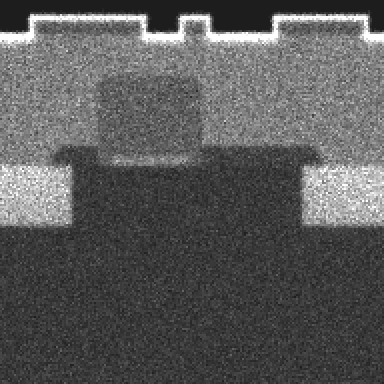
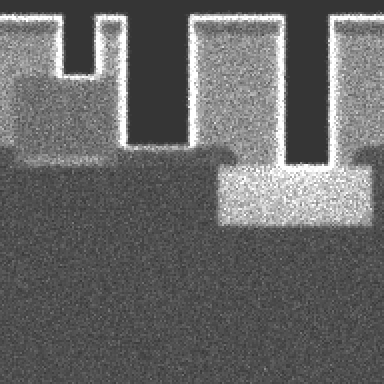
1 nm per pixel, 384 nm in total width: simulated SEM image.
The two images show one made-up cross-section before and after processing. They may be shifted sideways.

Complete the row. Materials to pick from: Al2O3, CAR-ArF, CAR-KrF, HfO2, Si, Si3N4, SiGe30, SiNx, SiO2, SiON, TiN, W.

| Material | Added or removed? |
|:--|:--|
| SiO2 | removed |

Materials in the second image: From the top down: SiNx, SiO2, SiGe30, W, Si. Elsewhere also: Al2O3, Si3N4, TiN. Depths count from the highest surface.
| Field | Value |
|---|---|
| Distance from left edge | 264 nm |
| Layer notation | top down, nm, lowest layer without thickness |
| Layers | SiNx 18, SiO2 132, W 60, Si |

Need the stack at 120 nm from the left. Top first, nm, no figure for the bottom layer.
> SiNx 18, SiO2 112, SiGe30 20, Si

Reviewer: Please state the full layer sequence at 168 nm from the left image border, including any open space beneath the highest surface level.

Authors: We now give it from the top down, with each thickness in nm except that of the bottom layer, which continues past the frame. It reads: empty 130, SiGe30 20, Si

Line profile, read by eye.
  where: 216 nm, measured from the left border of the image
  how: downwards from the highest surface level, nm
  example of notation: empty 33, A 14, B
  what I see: SiNx 18, SiO2 112, SiGe30 20, Si